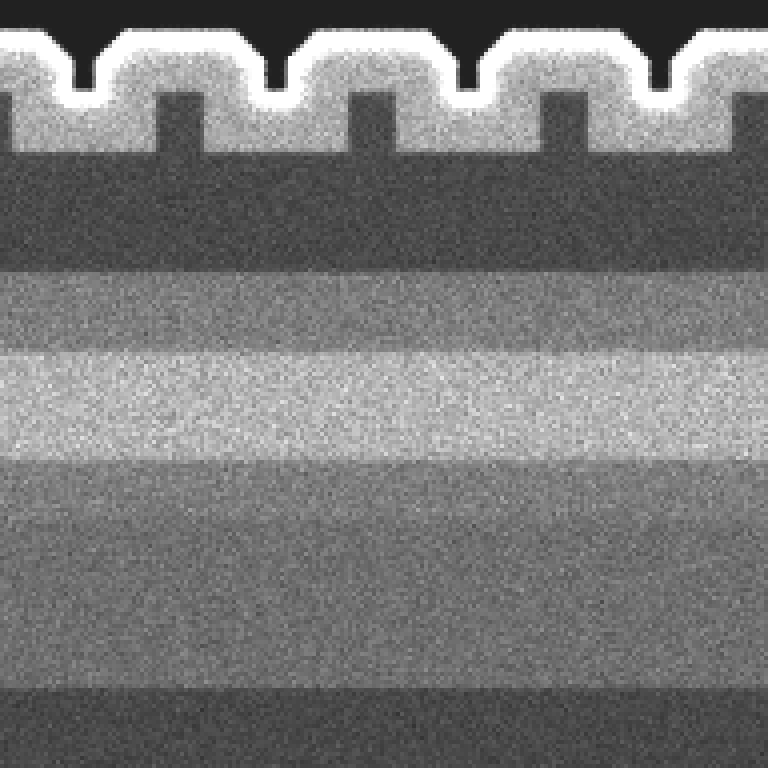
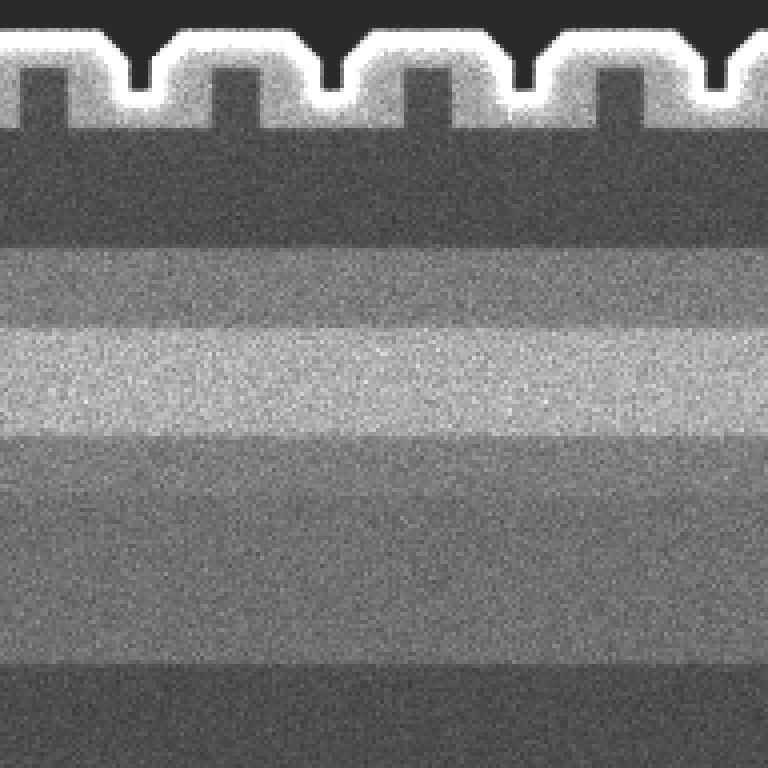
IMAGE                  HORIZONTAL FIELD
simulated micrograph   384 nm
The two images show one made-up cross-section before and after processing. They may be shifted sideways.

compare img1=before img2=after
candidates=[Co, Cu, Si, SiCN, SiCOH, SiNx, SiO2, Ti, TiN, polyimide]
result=removed:SiO2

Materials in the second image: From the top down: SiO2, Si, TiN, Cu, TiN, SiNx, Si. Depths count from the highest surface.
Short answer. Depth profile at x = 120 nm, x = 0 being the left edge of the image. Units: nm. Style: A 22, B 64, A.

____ SiO2 18, Si 90, TiN 40, Cu 54, TiN 30, SiNx 84, Si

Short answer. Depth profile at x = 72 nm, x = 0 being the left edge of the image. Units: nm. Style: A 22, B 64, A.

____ empty 30, SiO2 18, Si 60, TiN 40, Cu 54, TiN 30, SiNx 84, Si